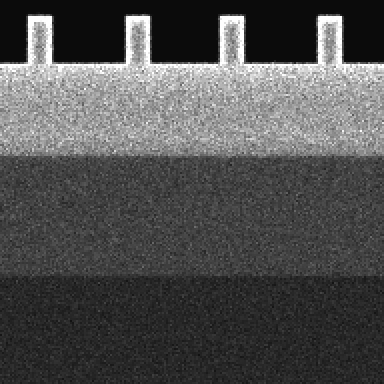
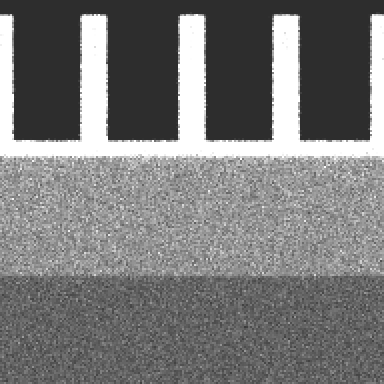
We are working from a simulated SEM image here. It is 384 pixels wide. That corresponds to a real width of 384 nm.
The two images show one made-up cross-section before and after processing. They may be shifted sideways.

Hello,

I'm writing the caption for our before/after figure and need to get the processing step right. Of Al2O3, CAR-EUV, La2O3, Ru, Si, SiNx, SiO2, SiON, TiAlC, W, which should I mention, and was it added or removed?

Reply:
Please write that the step removed W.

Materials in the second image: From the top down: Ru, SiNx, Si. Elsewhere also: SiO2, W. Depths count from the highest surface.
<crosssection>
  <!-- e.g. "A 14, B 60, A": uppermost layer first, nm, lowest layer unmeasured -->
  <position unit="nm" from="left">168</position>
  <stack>empty 126, Ru 14, SiNx 120, Si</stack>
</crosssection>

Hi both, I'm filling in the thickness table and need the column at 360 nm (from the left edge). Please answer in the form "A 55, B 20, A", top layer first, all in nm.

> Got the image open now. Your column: empty 126, Ru 14, SiNx 120, Si